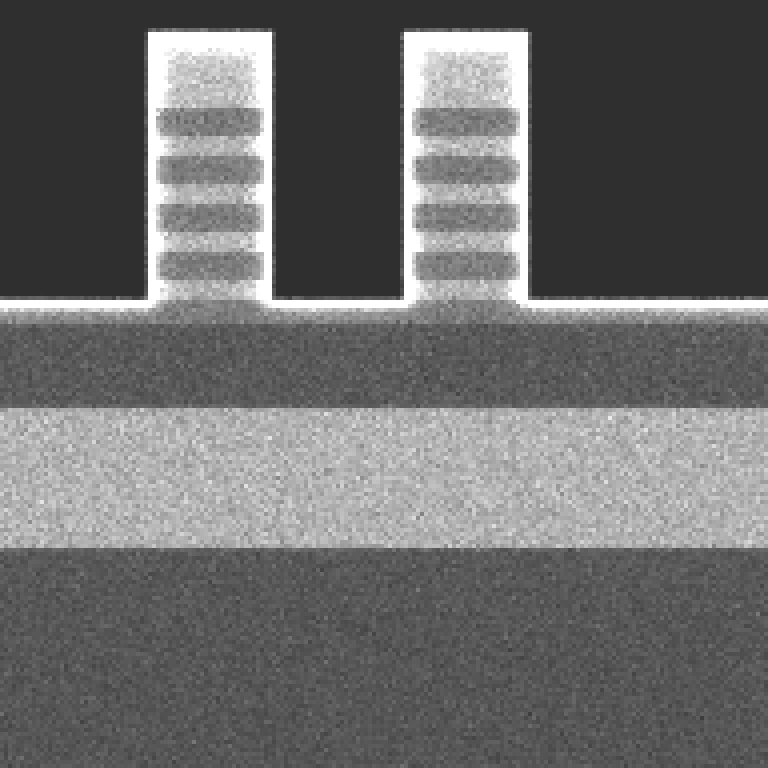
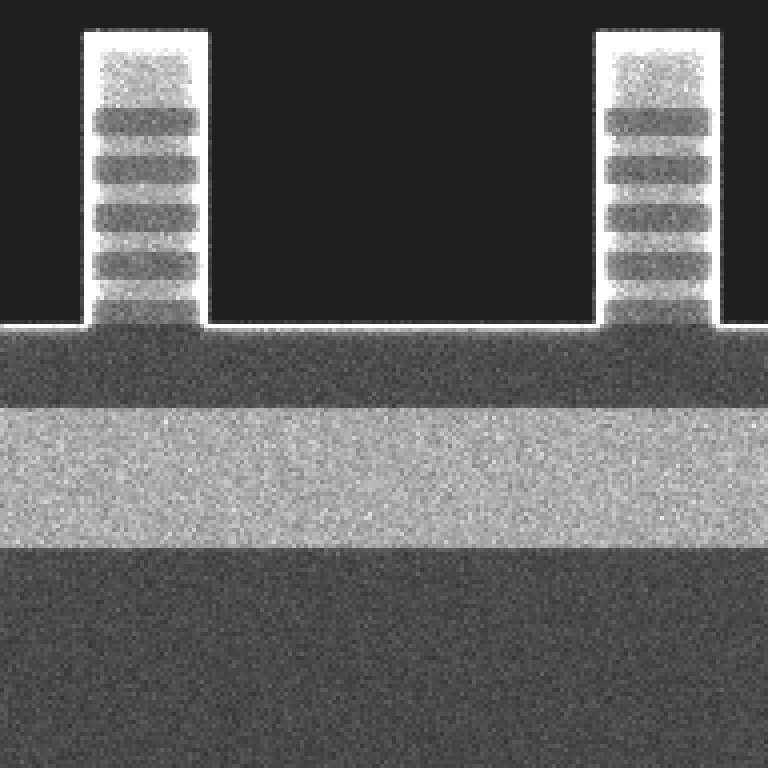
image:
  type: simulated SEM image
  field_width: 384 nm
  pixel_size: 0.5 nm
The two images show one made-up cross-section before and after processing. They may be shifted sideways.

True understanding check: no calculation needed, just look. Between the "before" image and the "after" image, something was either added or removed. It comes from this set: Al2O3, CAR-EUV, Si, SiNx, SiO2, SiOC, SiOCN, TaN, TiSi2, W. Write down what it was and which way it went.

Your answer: SiNx (removed)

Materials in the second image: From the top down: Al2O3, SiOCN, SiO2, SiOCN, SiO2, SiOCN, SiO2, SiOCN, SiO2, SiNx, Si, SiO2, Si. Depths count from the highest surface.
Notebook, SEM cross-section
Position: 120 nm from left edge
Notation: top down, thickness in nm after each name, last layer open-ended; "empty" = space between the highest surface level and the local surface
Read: empty 146, Si 42, SiO2 70, Si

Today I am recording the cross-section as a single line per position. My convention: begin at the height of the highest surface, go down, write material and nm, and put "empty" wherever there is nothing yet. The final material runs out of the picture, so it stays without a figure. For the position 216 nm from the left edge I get empty 146, Si 42, SiO2 70, Si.